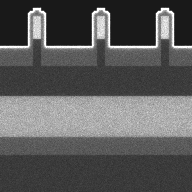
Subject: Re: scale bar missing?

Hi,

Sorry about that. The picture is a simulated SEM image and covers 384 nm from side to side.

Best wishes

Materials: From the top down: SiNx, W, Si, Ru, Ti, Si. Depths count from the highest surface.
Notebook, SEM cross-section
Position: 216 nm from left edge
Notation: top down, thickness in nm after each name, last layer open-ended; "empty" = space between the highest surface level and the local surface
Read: empty 8, SiNx 108, Si 60, Ru 82, Ti 36, Si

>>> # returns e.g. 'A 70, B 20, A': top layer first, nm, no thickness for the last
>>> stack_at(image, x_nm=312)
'empty 10, SiNx 106, Si 60, Ru 82, Ti 36, Si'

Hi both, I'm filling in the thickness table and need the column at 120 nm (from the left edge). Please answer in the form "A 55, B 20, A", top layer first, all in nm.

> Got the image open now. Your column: empty 76, SiNx 40, Si 60, Ru 82, Ti 36, Si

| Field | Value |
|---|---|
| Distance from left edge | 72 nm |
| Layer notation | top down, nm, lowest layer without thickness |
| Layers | SiNx 16, W 46, Si 114, Ru 82, Ti 36, Si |